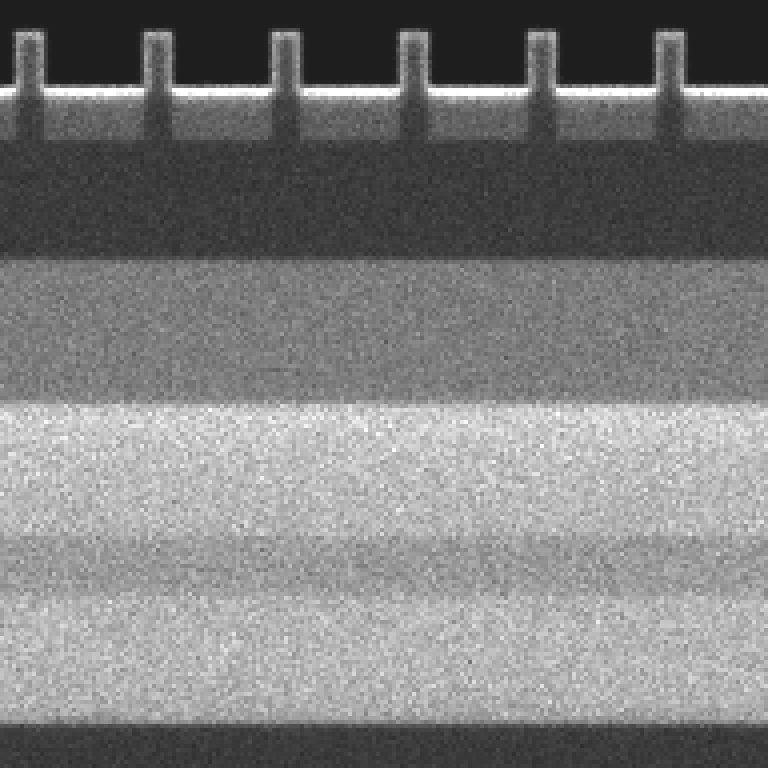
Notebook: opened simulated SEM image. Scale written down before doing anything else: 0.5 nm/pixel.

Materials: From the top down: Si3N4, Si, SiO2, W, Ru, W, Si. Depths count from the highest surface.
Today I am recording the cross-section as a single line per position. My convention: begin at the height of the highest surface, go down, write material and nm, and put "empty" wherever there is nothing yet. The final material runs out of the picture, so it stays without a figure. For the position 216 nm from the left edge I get empty 28, Si3N4 26, Si 60, SiO2 72, W 66, Ru 30, W 64, Si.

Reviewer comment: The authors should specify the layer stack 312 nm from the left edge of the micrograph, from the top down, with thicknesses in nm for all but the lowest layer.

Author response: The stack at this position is empty 28, Si3N4 26, Si 60, SiO2 72, W 66, Ru 30, W 64, Si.